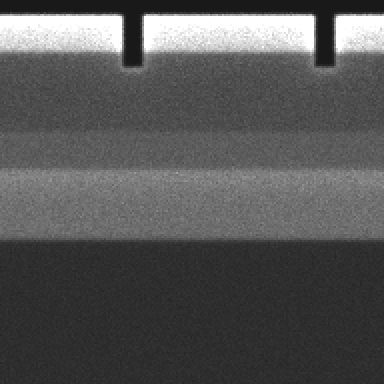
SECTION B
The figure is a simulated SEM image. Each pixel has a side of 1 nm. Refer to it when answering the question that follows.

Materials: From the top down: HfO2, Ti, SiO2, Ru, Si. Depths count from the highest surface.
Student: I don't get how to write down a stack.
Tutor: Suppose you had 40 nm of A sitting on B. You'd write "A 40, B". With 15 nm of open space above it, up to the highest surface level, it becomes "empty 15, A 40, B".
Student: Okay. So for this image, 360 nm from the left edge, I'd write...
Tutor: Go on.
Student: HfO2 36, Ti 80, SiO2 38, Ru 70, Si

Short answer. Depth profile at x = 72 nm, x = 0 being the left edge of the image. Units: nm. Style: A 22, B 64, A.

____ HfO2 36, Ti 80, SiO2 38, Ru 70, Si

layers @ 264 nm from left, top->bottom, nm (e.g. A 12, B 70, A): HfO2 36, Ti 80, SiO2 38, Ru 70, Si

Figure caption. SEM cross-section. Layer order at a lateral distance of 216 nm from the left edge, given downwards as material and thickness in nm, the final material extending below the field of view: HfO2 36, Ti 80, SiO2 38, Ru 70, Si